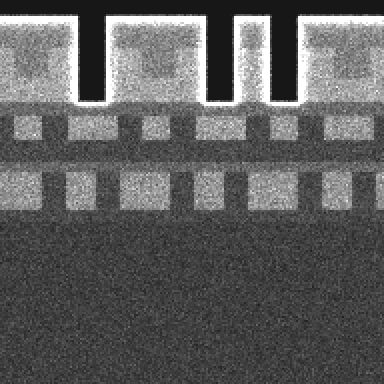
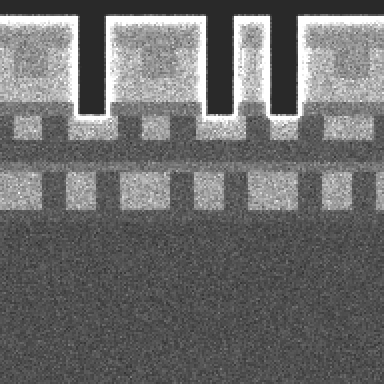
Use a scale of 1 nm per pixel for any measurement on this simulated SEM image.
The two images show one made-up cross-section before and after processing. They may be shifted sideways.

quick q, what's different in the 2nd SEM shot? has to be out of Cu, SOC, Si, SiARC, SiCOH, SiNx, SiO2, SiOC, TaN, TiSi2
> SiNx removed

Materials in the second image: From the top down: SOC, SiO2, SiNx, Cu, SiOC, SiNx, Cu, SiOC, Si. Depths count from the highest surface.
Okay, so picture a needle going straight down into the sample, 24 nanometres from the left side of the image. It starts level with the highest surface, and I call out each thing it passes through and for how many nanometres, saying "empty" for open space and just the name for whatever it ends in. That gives SOC 62, SiO2 24, SiNx 14, Cu 24, SiOC 22, SiNx 10, Cu 38, SiOC 12, Si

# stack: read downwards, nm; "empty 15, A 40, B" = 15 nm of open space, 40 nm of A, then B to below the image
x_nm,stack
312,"SOC 32, SiO2 54, SiNx 14, SiOC 46, SiNx 10, SiOC 50, Si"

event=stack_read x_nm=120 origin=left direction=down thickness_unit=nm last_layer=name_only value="SOC 32, SiO2 54, SiNx 14, SiOC 46, SiNx 10, Cu 38, SiOC 12, Si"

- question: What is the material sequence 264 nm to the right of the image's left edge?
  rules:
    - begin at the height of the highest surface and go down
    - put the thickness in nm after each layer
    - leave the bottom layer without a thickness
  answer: SOC 32, SiO2 54, SiNx 14, SiOC 46, SiNx 10, Cu 38, SiOC 12, Si